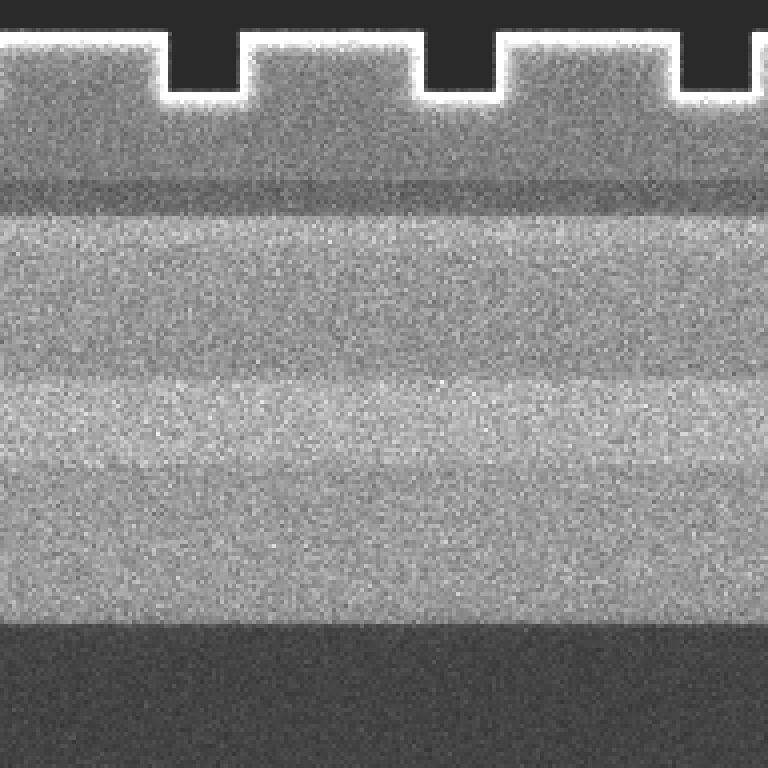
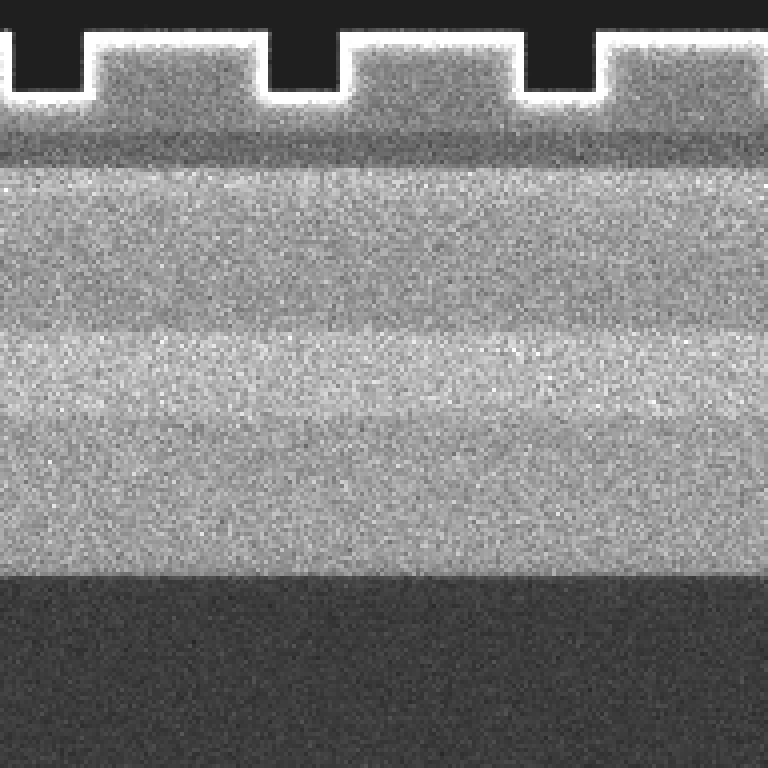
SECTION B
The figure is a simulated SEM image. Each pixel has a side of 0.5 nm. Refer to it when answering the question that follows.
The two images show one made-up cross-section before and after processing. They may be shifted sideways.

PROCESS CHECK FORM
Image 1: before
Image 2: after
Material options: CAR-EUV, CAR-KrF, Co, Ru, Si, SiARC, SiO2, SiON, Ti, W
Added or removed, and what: removed, SiO2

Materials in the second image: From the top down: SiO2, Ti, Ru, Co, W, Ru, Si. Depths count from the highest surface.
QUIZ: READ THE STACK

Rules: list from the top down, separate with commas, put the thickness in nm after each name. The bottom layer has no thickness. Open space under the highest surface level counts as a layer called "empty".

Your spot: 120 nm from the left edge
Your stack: SiO2 50, Ti 18, Ru 14, Co 68, W 42, Ru 80, Si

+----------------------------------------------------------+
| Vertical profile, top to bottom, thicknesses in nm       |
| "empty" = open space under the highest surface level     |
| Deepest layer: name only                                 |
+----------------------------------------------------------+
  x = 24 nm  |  empty 30, SiO2 20, Ti 18, Ru 14, Co 68, W 42, Ru 80, Si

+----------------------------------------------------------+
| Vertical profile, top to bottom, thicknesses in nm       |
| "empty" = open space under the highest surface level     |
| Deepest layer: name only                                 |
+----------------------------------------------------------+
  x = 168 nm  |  empty 30, SiO2 20, Ti 18, Ru 14, Co 68, W 42, Ru 80, Si